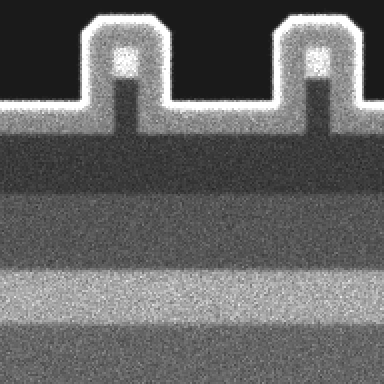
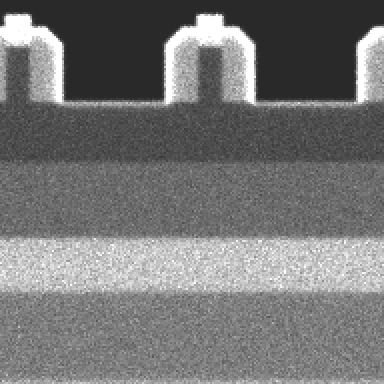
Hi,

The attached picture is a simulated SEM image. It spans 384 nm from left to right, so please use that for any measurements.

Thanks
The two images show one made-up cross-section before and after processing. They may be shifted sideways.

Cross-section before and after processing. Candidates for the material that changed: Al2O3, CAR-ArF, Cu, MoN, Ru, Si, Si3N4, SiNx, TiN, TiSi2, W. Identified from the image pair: Al2O3 (removed).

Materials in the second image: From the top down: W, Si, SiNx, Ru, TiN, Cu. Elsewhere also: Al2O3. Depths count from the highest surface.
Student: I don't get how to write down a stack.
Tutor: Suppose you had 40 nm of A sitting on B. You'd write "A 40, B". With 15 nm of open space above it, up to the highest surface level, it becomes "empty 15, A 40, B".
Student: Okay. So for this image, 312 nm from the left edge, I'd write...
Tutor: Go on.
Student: empty 86, Si 60, SiNx 76, Ru 54, TiN 88, Cu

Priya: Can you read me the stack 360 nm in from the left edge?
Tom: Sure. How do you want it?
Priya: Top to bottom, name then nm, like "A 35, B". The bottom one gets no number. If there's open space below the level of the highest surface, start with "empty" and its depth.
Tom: empty 26, Al2O3 60, Si 60, SiNx 76, Ru 54, TiN 88, Cu